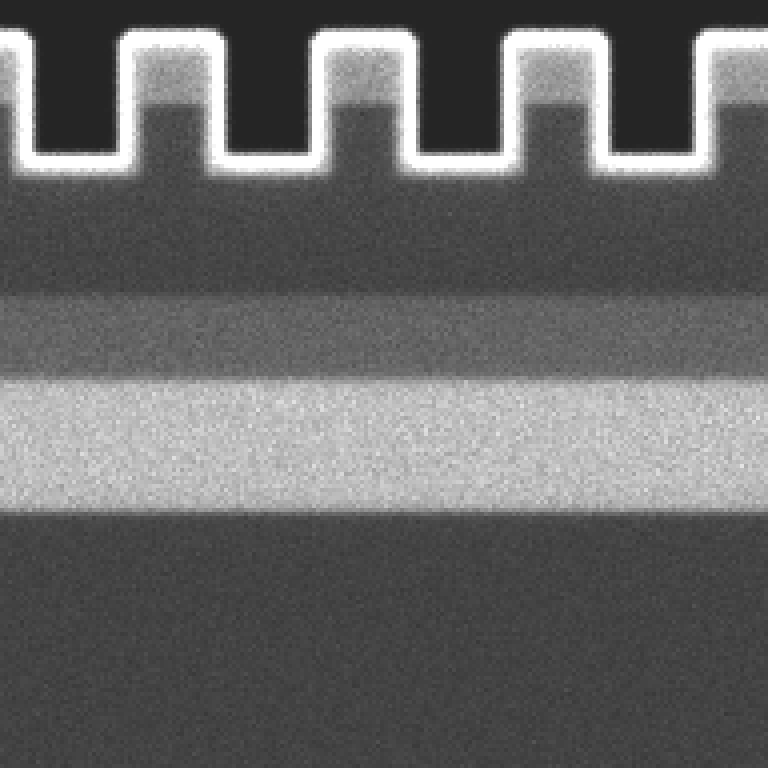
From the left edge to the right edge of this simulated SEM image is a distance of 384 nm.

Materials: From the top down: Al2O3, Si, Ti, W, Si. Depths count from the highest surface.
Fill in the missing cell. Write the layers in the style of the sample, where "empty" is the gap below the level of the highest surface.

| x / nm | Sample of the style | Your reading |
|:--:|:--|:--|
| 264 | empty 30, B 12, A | Al2O3 36, Si 96, Ti 42, W 66, Si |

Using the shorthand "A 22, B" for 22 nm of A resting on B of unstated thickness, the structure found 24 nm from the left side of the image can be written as empty 62, Al2O3 10, Si 60, Ti 42, W 66, Si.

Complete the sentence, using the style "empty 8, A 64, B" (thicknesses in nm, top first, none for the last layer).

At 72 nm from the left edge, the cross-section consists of Al2O3 36, Si 96, Ti 42, W 66, Si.